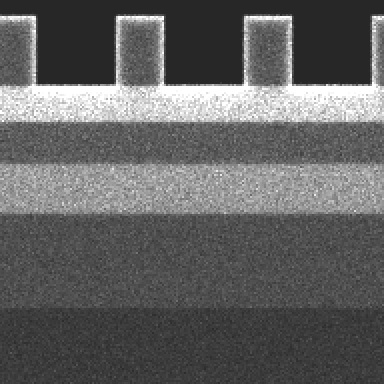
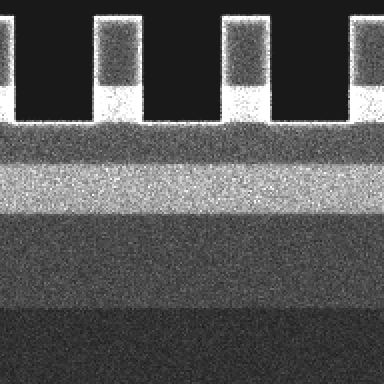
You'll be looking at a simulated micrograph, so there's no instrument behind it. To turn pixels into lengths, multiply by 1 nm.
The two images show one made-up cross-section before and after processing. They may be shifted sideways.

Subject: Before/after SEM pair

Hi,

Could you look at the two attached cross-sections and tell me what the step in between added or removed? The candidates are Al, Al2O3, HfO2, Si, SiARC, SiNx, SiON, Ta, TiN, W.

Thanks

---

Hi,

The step removed HfO2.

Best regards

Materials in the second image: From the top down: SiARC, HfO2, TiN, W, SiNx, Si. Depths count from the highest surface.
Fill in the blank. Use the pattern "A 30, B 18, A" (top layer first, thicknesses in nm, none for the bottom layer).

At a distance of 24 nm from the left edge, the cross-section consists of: empty 106, TiN 42, W 50, SiNx 94, Si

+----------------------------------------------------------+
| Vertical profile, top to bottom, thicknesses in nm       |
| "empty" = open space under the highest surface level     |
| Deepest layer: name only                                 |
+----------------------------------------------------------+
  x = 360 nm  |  SiARC 70, HfO2 36, TiN 42, W 50, SiNx 94, Si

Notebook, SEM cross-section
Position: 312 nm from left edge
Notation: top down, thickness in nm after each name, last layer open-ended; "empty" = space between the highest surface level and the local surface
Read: empty 106, TiN 42, W 50, SiNx 94, Si